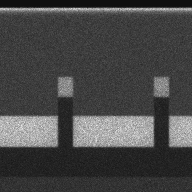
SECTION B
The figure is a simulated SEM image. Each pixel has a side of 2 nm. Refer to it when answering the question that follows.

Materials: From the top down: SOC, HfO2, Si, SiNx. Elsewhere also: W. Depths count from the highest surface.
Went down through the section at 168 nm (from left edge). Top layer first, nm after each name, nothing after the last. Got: SOC 216, HfO2 62, Si 60, SiNx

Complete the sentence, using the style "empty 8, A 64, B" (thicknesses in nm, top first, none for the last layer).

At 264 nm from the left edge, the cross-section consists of SOC 216, HfO2 62, Si 60, SiNx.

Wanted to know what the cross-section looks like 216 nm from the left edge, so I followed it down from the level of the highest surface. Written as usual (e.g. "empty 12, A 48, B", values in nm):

SOC 216, HfO2 62, Si 60, SiNx